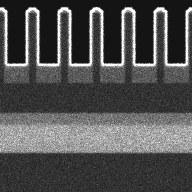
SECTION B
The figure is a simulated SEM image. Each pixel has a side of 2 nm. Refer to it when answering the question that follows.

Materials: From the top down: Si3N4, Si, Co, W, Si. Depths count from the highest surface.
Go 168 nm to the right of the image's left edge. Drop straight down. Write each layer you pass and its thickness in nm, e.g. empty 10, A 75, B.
empty 112, Si3N4 38, Si 60, Co 24, W 56, Si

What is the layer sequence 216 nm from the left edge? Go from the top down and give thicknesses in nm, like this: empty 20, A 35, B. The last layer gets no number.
empty 112, Si3N4 38, Si 60, Co 24, W 56, Si